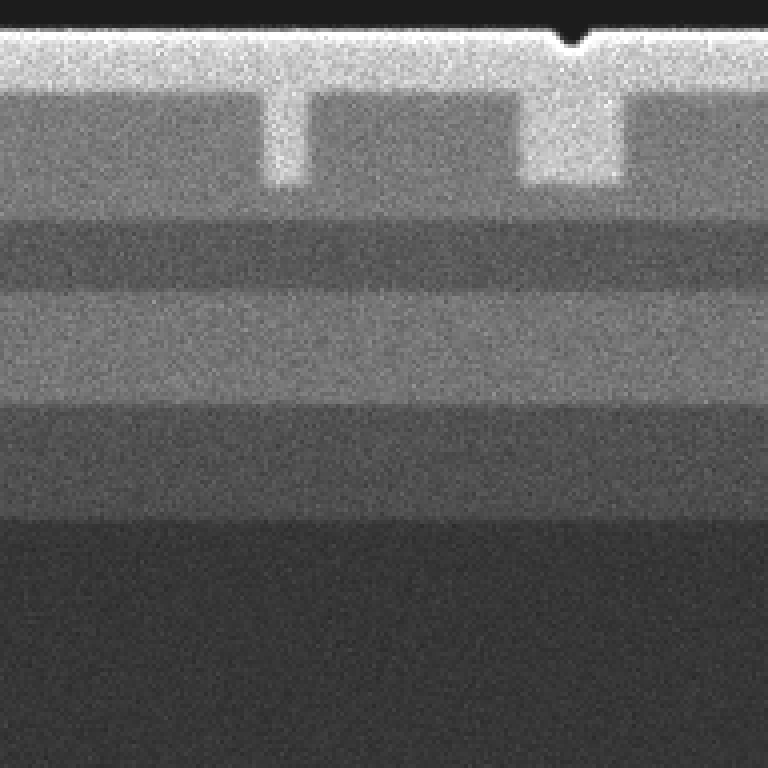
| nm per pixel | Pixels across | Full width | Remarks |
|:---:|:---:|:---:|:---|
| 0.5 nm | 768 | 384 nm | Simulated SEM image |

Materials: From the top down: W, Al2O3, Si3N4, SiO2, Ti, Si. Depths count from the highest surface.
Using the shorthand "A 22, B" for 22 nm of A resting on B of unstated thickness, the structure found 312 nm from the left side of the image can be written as W 30, Al2O3 64, Si3N4 36, SiO2 56, Ti 58, Si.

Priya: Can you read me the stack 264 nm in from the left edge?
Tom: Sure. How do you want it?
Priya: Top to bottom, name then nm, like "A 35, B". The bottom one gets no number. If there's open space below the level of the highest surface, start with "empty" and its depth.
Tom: W 76, Al2O3 18, Si3N4 36, SiO2 56, Ti 58, Si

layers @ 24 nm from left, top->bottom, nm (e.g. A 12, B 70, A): W 30, Al2O3 64, Si3N4 36, SiO2 56, Ti 58, Si